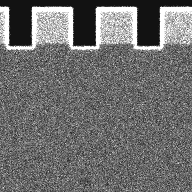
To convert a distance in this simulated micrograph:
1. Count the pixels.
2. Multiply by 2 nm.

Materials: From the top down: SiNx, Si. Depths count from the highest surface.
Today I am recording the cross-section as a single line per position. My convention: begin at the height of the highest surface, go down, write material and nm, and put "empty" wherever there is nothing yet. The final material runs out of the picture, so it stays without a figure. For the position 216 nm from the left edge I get SiNx 72, Si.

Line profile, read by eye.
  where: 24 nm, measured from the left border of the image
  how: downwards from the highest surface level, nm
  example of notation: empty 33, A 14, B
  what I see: empty 78, Si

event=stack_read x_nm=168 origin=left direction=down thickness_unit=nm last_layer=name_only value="empty 78, Si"